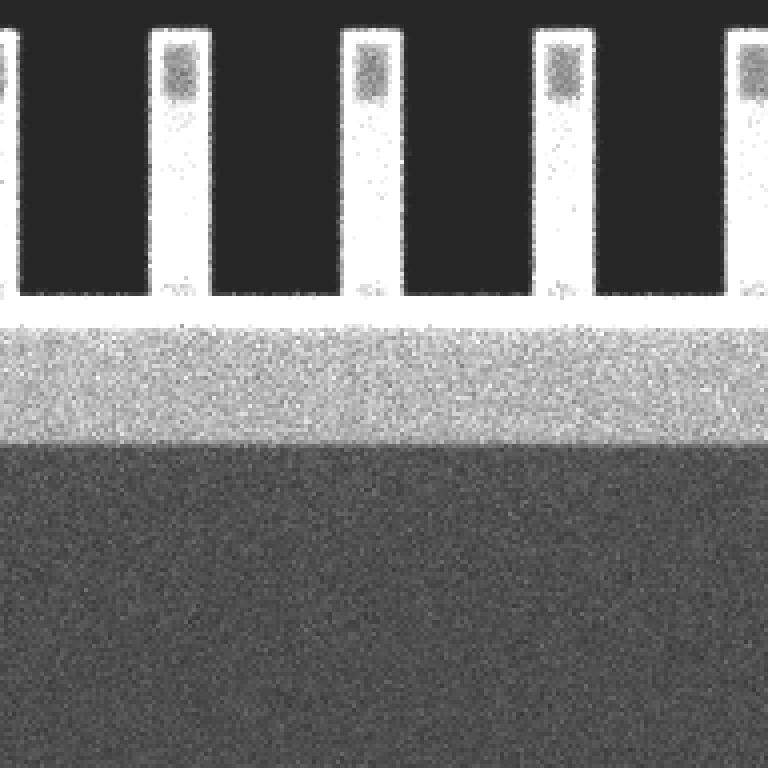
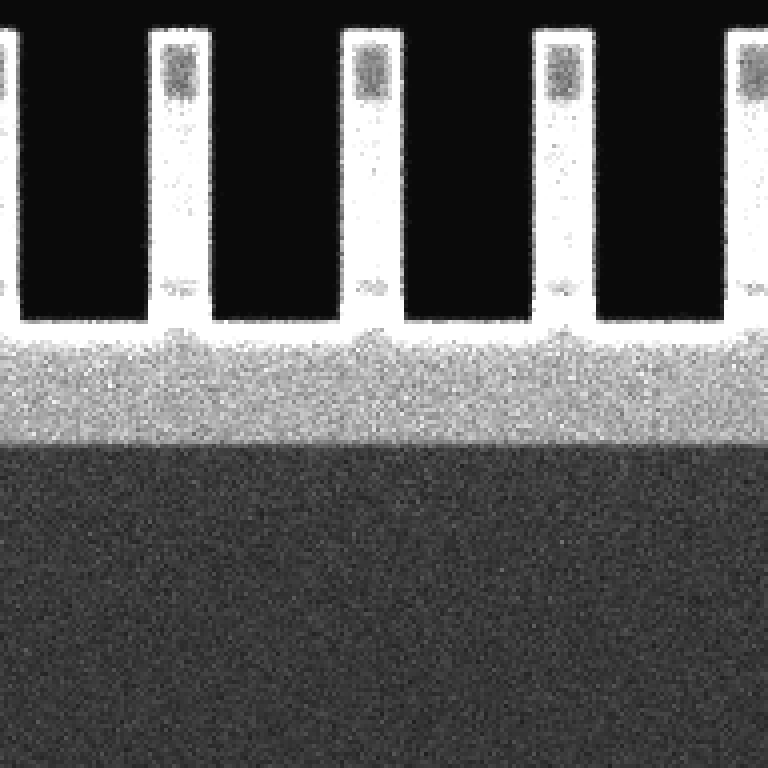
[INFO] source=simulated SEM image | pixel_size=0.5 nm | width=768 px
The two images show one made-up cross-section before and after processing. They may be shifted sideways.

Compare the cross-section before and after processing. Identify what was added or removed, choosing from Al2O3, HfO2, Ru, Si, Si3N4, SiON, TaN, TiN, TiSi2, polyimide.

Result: HfO2 removed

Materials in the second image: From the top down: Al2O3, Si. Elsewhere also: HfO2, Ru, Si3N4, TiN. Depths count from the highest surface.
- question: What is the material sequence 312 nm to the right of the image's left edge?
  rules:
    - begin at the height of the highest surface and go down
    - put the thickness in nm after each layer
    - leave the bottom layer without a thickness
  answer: empty 146, Al2O3 60, Si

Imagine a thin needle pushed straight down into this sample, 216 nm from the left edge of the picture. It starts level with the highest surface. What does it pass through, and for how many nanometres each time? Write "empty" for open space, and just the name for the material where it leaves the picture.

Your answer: empty 146, Al2O3 60, Si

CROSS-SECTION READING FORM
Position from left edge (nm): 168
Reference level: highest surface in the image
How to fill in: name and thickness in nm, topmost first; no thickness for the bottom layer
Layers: empty 146, Al2O3 60, Si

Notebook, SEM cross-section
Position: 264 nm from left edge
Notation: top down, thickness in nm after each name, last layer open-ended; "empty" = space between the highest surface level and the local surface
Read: empty 146, Al2O3 60, Si